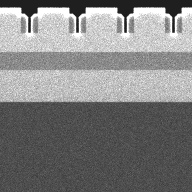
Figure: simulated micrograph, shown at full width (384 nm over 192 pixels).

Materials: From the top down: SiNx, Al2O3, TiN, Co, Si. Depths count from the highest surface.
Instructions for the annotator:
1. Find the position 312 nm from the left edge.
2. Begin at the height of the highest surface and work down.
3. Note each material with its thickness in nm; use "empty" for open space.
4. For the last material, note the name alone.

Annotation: Al2O3 88, TiN 36, Co 64, Si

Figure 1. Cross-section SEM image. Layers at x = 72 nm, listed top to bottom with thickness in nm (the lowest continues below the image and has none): empty 12, SiNx 38, Al2O3 38, TiN 36, Co 64, Si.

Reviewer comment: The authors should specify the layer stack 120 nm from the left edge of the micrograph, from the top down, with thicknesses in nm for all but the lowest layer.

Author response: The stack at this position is Al2O3 88, TiN 36, Co 64, Si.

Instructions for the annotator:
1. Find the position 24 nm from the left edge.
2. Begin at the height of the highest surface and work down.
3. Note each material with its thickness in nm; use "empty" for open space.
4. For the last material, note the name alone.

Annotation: Al2O3 88, TiN 36, Co 64, Si